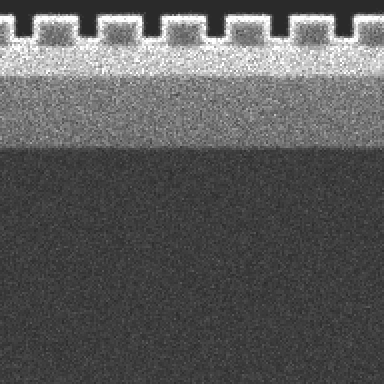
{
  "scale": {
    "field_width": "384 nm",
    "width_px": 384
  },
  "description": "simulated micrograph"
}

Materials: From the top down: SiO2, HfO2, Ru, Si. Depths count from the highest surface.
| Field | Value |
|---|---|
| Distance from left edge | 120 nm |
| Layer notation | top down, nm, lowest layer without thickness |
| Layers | SiO2 30, HfO2 30, Ru 72, Si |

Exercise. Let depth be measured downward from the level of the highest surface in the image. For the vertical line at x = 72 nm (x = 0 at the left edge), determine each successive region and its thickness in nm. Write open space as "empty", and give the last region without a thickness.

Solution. SiO2 30, HfO2 30, Ru 72, Si